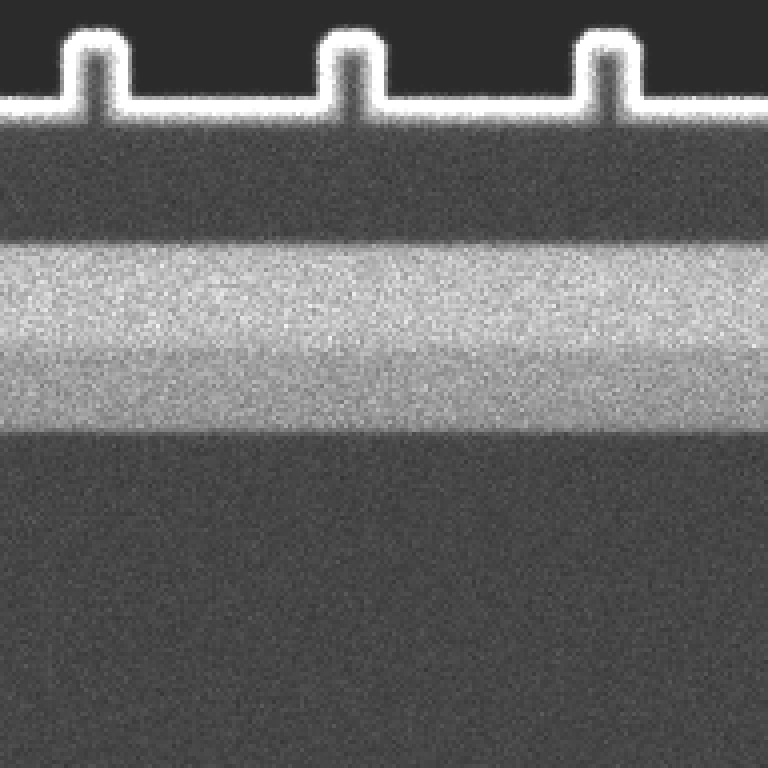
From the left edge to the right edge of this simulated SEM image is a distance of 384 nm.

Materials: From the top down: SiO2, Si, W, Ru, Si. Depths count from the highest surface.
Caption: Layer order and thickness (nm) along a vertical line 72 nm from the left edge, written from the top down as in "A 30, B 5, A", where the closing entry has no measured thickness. empty 34, SiO2 12, Si 60, W 52, Ru 42, Si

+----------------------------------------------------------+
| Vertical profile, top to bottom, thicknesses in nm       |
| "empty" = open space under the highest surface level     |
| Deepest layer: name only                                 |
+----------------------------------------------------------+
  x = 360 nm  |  empty 34, SiO2 12, Si 60, W 52, Ru 42, Si